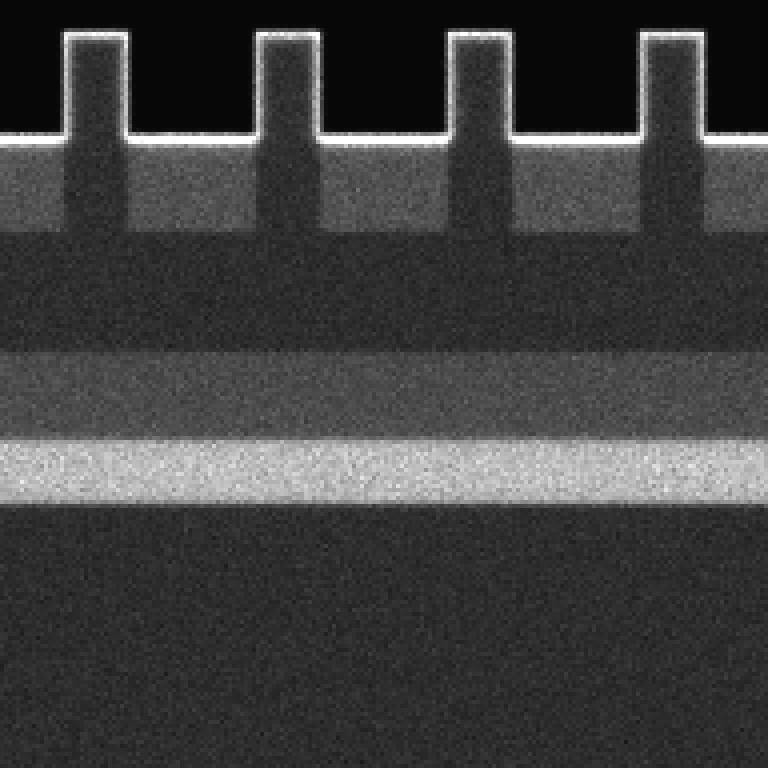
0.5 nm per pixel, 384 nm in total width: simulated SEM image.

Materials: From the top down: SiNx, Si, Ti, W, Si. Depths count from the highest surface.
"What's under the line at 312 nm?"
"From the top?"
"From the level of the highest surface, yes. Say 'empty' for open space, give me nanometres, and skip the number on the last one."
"empty 52, SiNx 48, Si 60, Ti 44, W 32, Si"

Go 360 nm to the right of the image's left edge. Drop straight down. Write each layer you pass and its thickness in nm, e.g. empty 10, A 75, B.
empty 52, SiNx 48, Si 60, Ti 44, W 32, Si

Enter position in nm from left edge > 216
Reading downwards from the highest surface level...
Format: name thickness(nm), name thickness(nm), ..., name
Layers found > empty 52, SiNx 48, Si 60, Ti 44, W 32, Si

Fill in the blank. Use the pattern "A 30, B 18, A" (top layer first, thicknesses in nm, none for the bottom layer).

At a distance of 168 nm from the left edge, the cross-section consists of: empty 52, SiNx 48, Si 60, Ti 44, W 32, Si